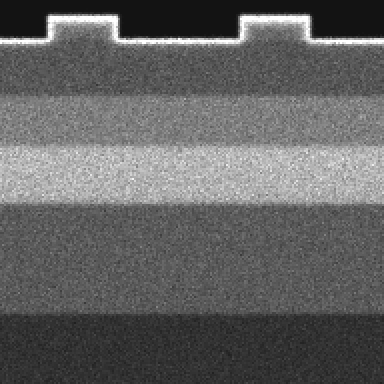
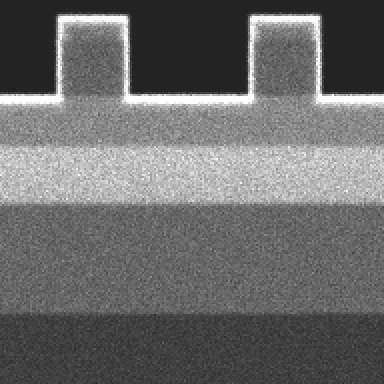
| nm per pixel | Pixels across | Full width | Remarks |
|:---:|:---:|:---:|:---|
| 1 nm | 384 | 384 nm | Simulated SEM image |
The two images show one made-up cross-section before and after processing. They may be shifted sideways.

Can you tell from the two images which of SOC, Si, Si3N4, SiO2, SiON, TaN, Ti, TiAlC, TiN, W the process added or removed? Yes, it removed TiN.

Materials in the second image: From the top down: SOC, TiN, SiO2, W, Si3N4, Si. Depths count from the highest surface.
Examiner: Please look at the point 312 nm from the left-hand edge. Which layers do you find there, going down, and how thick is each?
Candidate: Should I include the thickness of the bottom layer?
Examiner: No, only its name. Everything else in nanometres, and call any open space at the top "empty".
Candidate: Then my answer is SOC 24, TiN 56, SiO2 50, W 58, Si3N4 110, Si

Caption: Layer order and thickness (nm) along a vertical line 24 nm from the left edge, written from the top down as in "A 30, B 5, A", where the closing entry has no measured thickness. empty 80, SiO2 50, W 58, Si3N4 110, Si